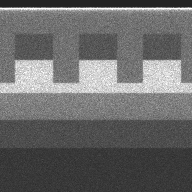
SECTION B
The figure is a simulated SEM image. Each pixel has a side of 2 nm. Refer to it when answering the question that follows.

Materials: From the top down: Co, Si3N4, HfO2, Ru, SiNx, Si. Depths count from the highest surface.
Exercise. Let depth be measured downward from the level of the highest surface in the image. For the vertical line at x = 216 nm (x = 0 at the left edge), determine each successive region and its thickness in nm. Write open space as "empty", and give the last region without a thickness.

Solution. Co 52, Si3N4 52, HfO2 66, Ru 54, SiNx 56, Si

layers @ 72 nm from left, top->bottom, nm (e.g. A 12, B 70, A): Co 52, Si3N4 52, HfO2 66, Ru 54, SiNx 56, Si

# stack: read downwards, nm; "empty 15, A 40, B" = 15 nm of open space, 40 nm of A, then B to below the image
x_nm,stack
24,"Co 150, HfO2 20, Ru 54, SiNx 56, Si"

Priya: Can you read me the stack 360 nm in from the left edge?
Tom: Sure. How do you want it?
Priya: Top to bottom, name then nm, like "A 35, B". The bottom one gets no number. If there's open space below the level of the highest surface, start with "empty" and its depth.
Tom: Co 52, Si3N4 52, HfO2 66, Ru 54, SiNx 56, Si